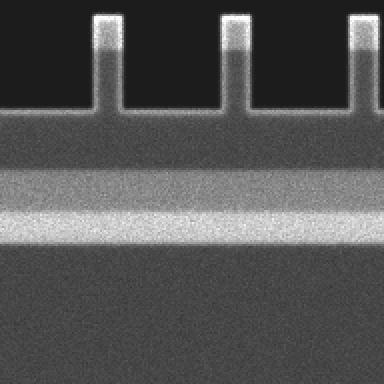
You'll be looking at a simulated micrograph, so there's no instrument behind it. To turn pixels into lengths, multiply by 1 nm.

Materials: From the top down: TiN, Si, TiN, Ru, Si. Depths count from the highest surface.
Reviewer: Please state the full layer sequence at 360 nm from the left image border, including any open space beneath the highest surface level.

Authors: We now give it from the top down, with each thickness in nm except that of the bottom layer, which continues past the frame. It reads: TiN 34, Si 120, TiN 42, Ru 32, Si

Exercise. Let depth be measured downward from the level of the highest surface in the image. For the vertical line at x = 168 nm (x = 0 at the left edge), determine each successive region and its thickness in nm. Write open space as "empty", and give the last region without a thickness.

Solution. empty 94, Si 60, TiN 42, Ru 32, Si